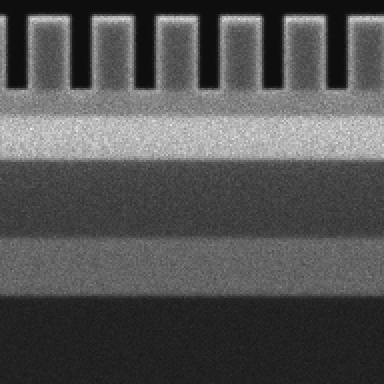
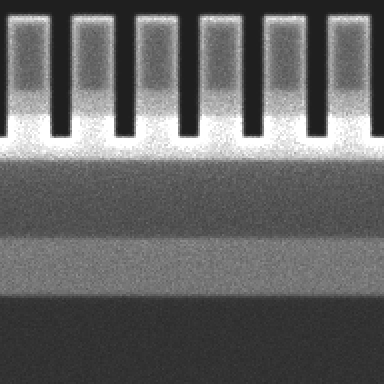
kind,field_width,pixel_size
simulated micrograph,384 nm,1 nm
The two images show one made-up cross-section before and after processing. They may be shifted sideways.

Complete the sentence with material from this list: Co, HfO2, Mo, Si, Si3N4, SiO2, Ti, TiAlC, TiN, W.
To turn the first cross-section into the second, Co and HfO2 must be removed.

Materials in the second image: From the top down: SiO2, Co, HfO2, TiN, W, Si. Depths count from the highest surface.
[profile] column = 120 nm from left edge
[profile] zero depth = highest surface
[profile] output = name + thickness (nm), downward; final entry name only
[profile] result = empty 122, HfO2 22, TiN 78, W 58, Si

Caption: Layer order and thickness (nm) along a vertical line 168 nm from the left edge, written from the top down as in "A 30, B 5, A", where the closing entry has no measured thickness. SiO2 74, Co 26, HfO2 44, TiN 78, W 58, Si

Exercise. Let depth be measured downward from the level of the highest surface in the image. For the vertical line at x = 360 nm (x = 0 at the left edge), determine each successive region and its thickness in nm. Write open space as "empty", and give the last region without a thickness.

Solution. SiO2 74, Co 26, HfO2 44, TiN 78, W 58, Si